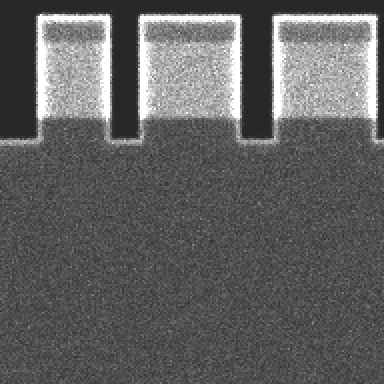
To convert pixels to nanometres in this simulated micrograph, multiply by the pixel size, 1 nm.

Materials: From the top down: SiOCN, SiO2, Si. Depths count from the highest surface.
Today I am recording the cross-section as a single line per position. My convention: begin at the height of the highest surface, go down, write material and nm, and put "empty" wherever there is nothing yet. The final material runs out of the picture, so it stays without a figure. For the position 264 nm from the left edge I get empty 124, Si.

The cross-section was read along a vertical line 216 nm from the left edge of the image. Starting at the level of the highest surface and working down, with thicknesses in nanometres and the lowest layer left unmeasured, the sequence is SiOCN 26, SiO2 76, Si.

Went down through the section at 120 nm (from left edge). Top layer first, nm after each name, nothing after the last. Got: empty 124, Si